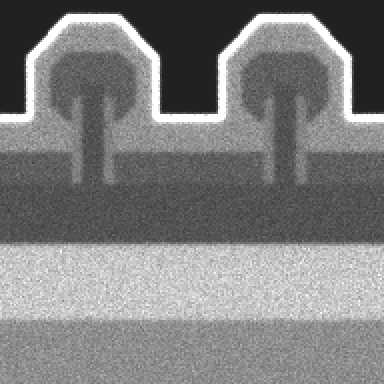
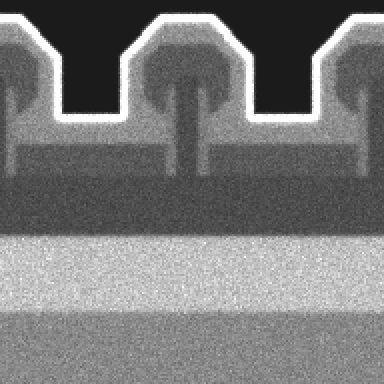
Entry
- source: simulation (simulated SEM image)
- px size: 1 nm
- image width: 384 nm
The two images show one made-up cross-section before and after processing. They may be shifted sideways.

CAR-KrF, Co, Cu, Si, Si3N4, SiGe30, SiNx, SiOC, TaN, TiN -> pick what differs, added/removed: Si3N4 removed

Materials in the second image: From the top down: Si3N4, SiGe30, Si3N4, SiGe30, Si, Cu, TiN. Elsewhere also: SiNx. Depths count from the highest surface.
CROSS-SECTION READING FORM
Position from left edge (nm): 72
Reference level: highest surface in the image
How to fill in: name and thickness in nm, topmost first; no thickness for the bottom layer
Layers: empty 100, Si3N4 28, SiGe30 32, Si 60, Cu 76, TiN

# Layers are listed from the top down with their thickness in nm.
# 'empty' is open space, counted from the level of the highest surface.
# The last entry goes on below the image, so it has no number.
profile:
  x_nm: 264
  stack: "empty 100, Si3N4 28, SiGe30 32, Si 60, Cu 76, TiN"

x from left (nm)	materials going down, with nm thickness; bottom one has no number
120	empty 100, Si3N4 28, SiGe30 32, Si 60, Cu 76, TiN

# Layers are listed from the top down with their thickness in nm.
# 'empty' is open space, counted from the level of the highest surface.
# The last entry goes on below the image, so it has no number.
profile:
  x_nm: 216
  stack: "empty 4, Si3N4 28, SiGe30 62, Si3N4 34, SiGe30 32, Si 60, Cu 76, TiN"